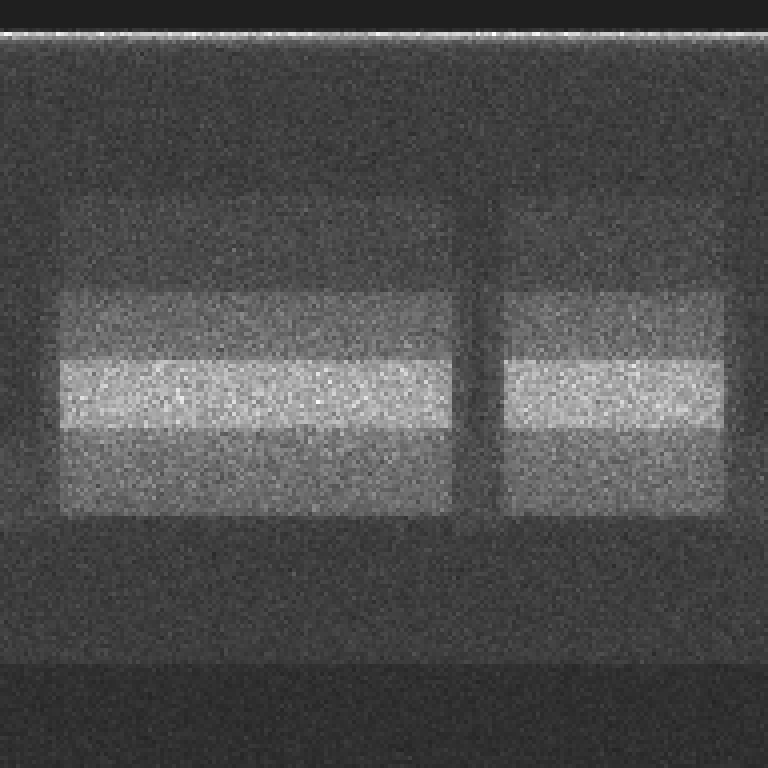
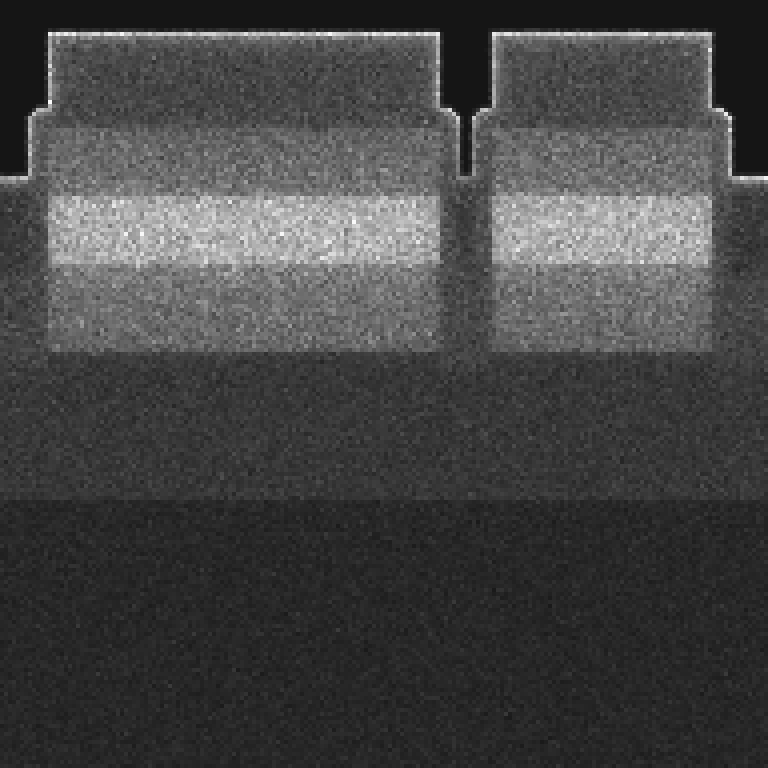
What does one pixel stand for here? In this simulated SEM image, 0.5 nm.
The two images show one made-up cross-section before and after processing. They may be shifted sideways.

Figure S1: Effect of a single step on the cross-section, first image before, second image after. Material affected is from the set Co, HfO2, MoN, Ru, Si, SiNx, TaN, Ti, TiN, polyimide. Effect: removed SiNx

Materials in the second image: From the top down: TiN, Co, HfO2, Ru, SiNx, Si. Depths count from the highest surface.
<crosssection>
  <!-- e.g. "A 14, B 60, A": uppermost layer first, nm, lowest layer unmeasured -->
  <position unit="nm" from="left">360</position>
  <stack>empty 38, TiN 130, SiNx 66, Si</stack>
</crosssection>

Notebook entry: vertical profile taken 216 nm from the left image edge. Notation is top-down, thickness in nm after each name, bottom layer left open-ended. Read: TiN 48, Co 34, HfO2 34, Ru 44, SiNx 74, Si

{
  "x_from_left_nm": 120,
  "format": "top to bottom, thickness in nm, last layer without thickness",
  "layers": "TiN 48, Co 34, HfO2 34, Ru 44, SiNx 74, Si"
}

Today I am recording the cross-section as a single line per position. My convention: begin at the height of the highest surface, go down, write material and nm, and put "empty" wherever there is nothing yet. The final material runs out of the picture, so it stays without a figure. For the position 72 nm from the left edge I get TiN 48, Co 34, HfO2 34, Ru 44, SiNx 74, Si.